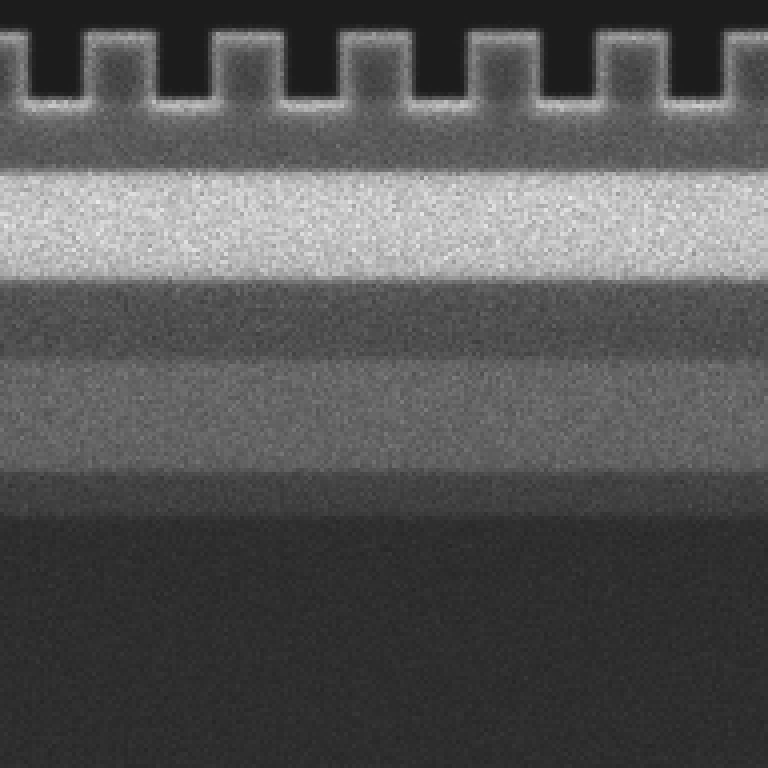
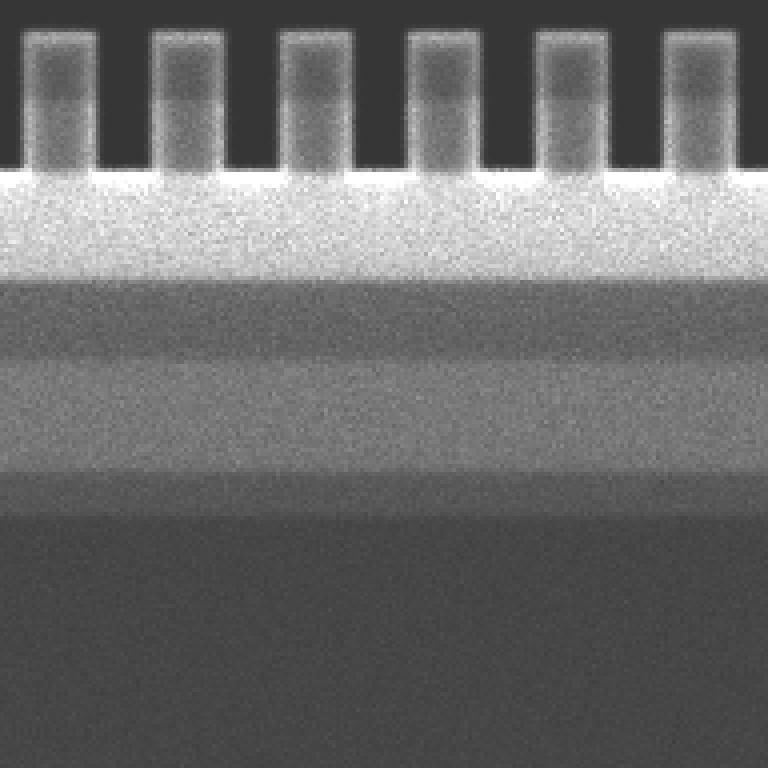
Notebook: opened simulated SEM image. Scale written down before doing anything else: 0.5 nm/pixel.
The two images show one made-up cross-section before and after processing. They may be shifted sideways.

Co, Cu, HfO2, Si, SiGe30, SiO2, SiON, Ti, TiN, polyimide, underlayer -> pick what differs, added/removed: SiO2 removed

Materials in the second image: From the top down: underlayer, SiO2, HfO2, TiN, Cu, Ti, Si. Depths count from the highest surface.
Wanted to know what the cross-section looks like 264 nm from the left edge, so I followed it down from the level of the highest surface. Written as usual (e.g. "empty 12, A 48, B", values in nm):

empty 70, HfO2 54, TiN 40, Cu 56, Ti 22, Si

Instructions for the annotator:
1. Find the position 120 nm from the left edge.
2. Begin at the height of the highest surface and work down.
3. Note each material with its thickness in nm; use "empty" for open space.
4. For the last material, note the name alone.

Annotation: empty 70, HfO2 54, TiN 40, Cu 56, Ti 22, Si